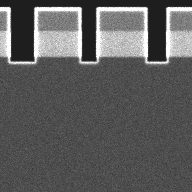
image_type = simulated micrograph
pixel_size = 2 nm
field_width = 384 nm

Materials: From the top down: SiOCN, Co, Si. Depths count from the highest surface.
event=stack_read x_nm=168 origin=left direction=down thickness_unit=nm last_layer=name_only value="empty 108, Si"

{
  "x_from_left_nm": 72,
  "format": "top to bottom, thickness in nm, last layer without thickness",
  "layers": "SiOCN 46, Co 52, Si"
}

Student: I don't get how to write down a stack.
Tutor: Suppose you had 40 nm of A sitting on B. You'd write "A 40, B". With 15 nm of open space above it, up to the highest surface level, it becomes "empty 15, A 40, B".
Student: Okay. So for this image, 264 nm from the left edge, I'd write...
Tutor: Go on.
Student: SiOCN 46, Co 52, Si